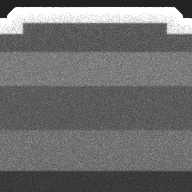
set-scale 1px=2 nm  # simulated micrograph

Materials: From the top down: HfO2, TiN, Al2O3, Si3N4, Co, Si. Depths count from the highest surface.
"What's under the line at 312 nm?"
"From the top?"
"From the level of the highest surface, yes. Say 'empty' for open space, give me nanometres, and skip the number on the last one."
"HfO2 30, TiN 58, Al2O3 68, Si3N4 88, Co 82, Si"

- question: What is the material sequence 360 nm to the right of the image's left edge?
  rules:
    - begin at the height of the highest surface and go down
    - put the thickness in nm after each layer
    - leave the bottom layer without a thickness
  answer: empty 12, HfO2 40, TiN 36, Al2O3 68, Si3N4 88, Co 82, Si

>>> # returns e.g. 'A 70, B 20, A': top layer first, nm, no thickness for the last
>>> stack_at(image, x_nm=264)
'HfO2 30, TiN 58, Al2O3 68, Si3N4 88, Co 82, Si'